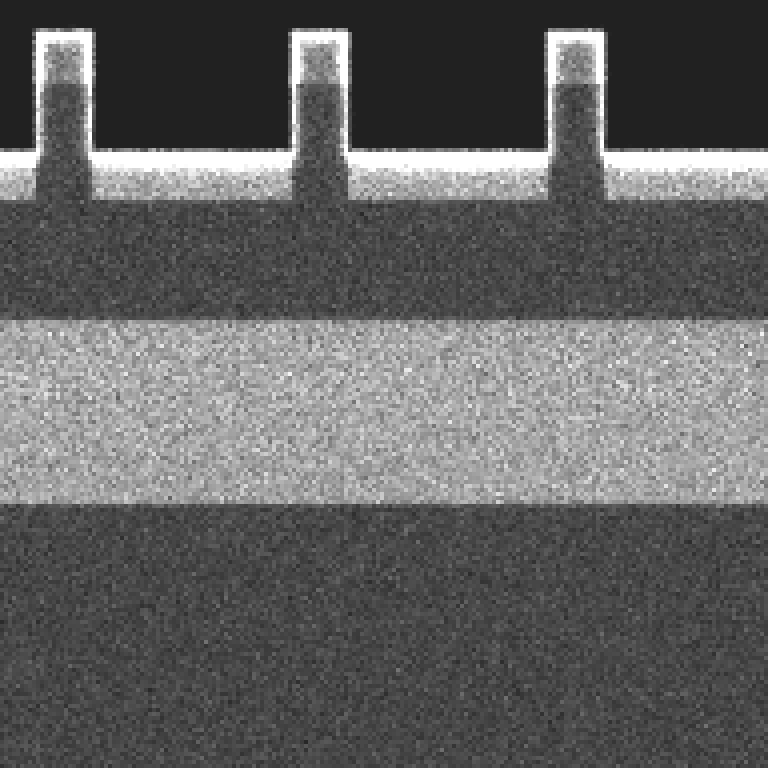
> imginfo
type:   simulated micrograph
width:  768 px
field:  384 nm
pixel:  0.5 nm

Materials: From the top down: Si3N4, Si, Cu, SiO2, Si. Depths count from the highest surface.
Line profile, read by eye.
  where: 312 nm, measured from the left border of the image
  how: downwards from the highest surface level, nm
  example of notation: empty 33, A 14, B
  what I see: empty 60, SiO2 24, Si 60, Cu 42, SiO2 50, Si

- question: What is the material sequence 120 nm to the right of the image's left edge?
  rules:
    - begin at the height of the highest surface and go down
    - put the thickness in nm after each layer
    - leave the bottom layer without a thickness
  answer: empty 60, SiO2 24, Si 60, Cu 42, SiO2 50, Si